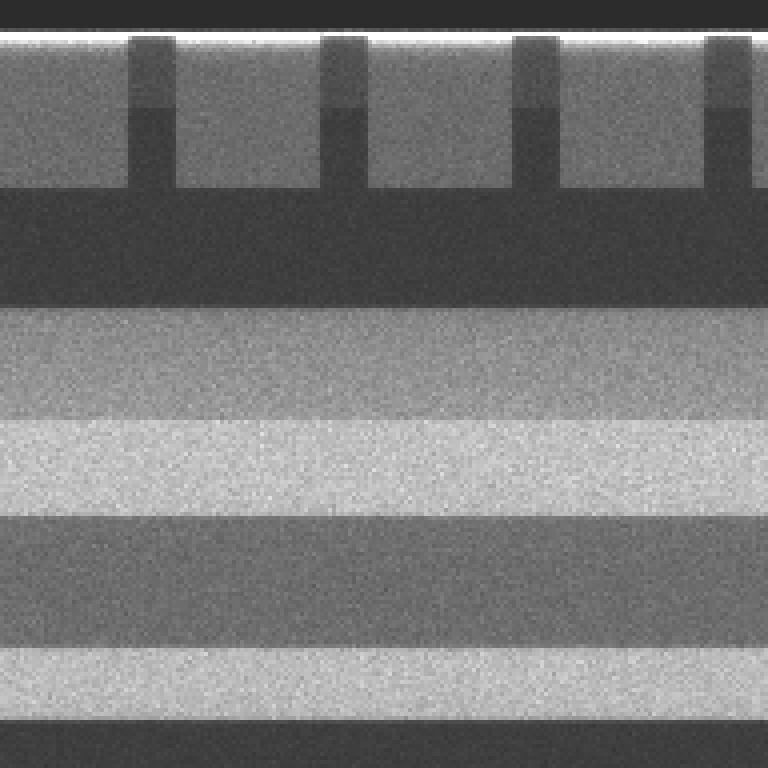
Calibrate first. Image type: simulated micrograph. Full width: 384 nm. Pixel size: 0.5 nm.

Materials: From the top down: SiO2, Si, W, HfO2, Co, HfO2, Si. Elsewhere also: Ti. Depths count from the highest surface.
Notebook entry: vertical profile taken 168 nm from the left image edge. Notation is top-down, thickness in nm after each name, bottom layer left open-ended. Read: Ti 38, Si 100, W 56, HfO2 48, Co 66, HfO2 36, Si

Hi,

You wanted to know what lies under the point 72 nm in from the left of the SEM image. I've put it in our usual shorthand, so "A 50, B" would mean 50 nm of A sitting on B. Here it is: Ti 38, Si 100, W 56, HfO2 48, Co 66, HfO2 36, Si